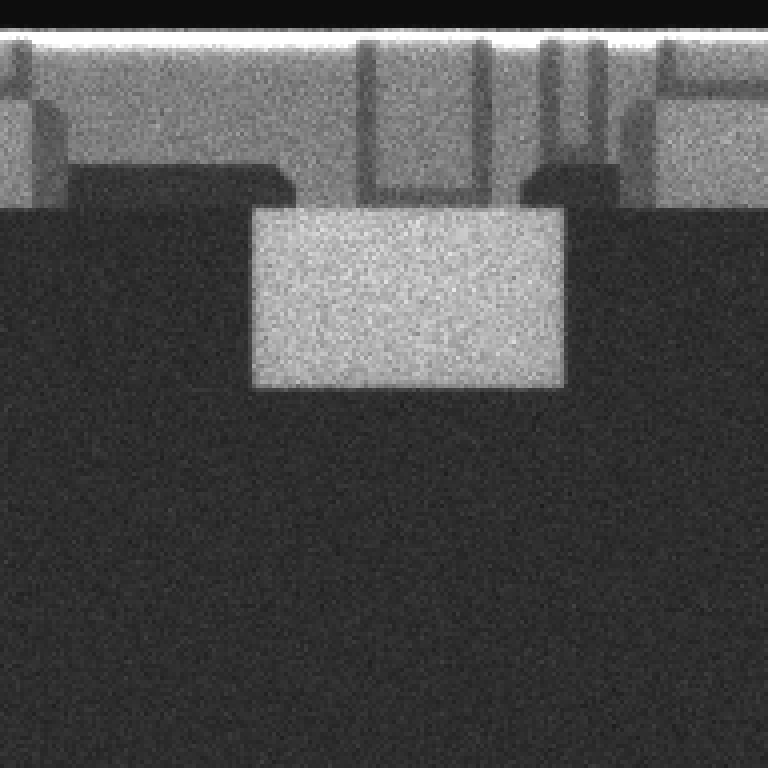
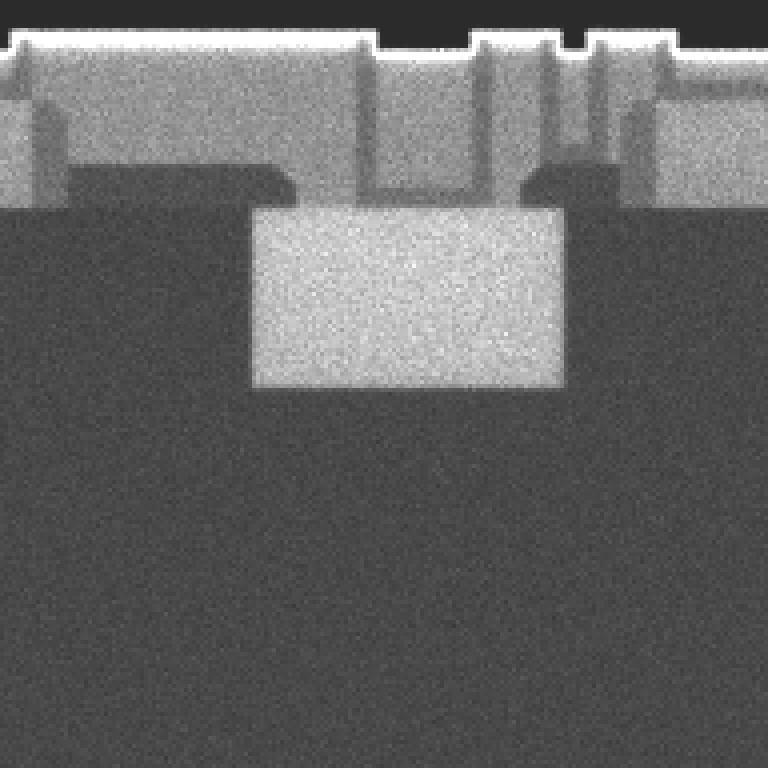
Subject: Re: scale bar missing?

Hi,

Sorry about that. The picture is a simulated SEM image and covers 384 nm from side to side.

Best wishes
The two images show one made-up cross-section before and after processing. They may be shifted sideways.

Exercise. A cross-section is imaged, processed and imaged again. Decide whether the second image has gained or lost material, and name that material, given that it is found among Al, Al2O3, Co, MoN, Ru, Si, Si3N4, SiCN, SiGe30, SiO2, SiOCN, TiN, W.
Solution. removed: Co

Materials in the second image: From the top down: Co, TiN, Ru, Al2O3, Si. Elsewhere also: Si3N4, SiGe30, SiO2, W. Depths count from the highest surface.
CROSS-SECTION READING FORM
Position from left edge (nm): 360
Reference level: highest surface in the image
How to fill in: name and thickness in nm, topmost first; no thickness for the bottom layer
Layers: empty 10, Co 14, TiN 10, Ru 44, Al2O3 10, Si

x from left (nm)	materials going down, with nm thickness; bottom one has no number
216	empty 10, Co 68, TiN 10, W 90, Si